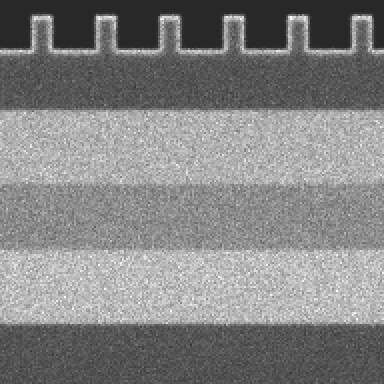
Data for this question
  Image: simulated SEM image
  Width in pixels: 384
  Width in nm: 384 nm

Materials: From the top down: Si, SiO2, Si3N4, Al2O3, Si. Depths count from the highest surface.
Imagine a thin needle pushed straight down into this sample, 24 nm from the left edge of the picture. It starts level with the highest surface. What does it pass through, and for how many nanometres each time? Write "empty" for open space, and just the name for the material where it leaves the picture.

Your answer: empty 34, Si 60, SiO2 74, Si3N4 66, Al2O3 74, Si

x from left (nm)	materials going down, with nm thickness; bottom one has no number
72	empty 34, Si 60, SiO2 74, Si3N4 66, Al2O3 74, Si